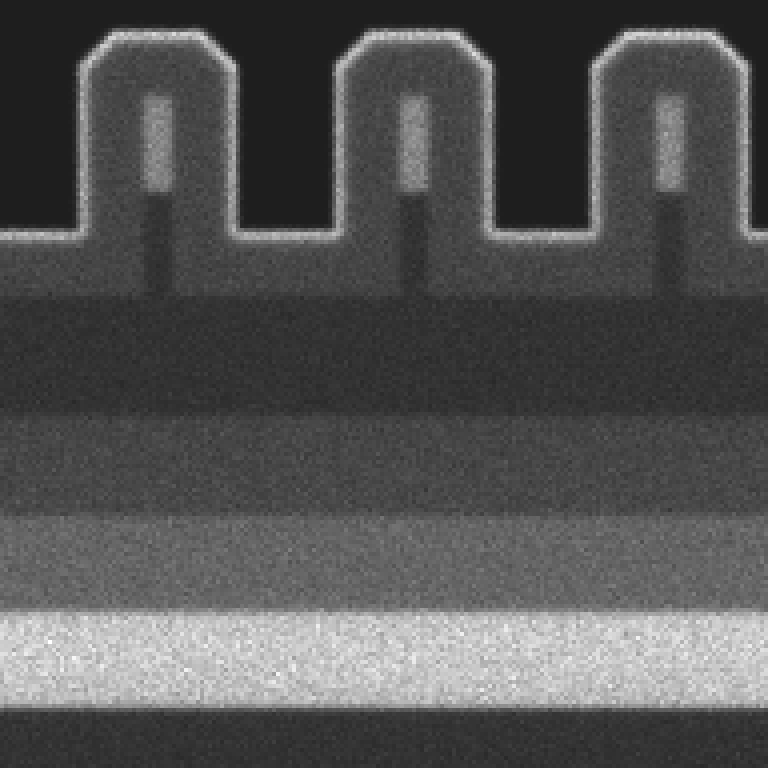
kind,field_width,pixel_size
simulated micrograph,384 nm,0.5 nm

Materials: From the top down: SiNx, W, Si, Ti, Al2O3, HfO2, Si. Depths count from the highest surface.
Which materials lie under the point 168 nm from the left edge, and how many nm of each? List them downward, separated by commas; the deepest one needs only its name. empty 16, SiNx 116, Si 60, Ti 50, Al2O3 48, HfO2 48, Si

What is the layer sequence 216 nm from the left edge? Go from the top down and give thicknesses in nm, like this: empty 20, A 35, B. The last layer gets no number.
SiNx 132, Si 60, Ti 50, Al2O3 48, HfO2 48, Si